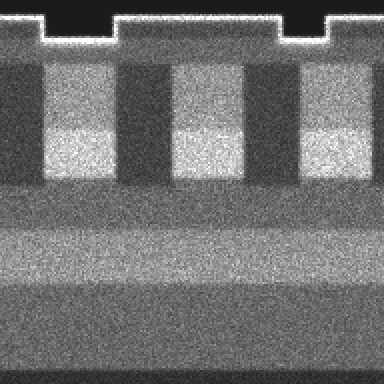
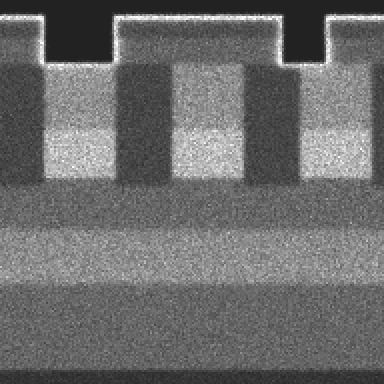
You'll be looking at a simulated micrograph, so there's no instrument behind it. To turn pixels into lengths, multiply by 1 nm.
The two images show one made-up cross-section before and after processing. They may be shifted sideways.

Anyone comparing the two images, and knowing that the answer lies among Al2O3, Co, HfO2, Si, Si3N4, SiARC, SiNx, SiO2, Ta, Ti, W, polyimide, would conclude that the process removed SiO2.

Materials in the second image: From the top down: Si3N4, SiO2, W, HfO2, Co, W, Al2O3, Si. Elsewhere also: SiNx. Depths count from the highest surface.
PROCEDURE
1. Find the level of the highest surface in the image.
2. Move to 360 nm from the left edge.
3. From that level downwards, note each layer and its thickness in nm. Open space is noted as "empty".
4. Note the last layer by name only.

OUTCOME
Si3N4 22, SiO2 26, W 66, HfO2 48, Co 52, W 54, Al2O3 86, Si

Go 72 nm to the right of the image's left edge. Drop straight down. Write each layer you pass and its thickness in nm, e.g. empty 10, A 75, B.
empty 48, W 66, HfO2 48, Co 52, W 54, Al2O3 86, Si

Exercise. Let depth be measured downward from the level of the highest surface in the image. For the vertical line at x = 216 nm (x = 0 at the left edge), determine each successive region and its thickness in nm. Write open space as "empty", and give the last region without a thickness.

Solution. Si3N4 22, SiO2 26, W 66, HfO2 48, Co 52, W 54, Al2O3 86, Si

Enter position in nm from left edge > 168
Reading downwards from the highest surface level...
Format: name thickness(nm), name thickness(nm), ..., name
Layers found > Si3N4 22, SiO2 26, SiNx 122, Co 44, W 54, Al2O3 86, Si